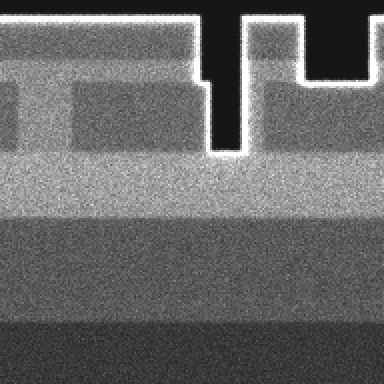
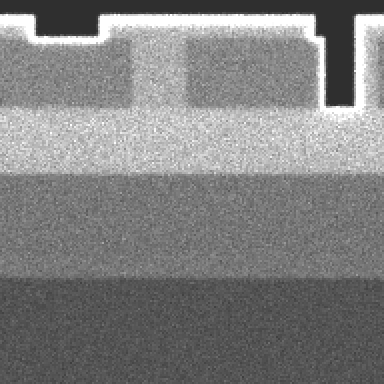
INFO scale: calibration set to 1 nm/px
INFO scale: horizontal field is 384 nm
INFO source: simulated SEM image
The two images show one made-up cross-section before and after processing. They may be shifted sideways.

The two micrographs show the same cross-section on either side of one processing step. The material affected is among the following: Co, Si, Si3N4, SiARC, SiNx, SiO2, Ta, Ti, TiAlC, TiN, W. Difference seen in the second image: SiARC removed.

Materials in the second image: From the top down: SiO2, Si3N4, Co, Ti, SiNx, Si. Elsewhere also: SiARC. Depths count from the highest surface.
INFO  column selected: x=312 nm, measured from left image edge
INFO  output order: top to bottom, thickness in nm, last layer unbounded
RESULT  SiO2 22, Si3N4 70, Co 66, Ti 80, SiNx 24, Si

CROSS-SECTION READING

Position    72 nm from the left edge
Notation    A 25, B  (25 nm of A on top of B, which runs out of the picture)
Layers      empty 22, Si3N4 70, Co 66, Ti 80, SiNx 24, Si